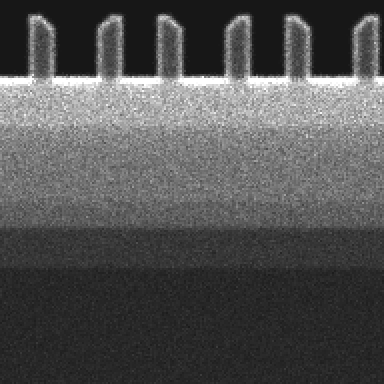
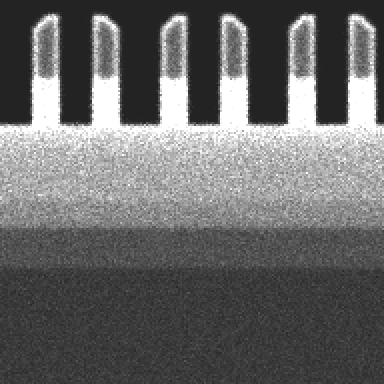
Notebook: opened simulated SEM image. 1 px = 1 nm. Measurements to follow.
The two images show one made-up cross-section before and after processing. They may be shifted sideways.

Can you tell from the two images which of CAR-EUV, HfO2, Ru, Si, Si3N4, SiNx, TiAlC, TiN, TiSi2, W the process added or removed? Yes, it removed HfO2.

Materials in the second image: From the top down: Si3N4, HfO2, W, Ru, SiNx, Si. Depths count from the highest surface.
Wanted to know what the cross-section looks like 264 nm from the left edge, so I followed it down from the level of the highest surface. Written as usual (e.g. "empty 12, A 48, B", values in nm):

empty 110, W 76, Ru 26, SiNx 40, Si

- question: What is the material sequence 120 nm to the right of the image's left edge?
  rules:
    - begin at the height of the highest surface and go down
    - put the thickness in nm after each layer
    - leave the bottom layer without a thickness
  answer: empty 110, W 76, Ru 26, SiNx 40, Si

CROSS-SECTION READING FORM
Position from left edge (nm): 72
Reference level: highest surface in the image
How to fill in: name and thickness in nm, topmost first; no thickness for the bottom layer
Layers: empty 110, W 76, Ru 26, SiNx 40, Si